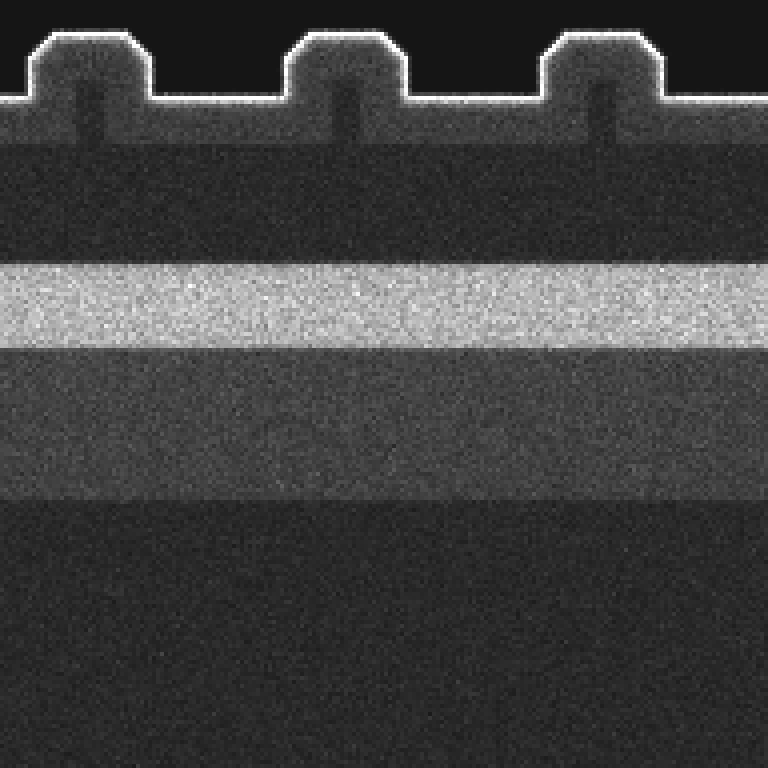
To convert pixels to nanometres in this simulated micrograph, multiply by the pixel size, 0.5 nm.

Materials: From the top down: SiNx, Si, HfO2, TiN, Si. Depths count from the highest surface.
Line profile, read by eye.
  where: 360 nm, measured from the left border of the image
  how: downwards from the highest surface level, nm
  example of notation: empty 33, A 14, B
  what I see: empty 32, SiNx 24, Si 60, HfO2 42, TiN 76, Si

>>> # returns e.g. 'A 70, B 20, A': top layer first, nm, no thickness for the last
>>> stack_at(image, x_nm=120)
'empty 32, SiNx 24, Si 60, HfO2 42, TiN 76, Si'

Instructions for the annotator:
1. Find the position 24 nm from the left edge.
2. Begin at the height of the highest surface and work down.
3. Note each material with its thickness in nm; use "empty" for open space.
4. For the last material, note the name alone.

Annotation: empty 2, SiNx 54, Si 60, HfO2 42, TiN 76, Si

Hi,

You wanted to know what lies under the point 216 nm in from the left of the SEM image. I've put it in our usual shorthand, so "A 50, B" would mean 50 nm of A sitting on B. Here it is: empty 32, SiNx 24, Si 60, HfO2 42, TiN 76, Si